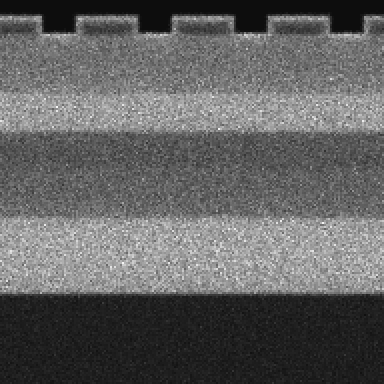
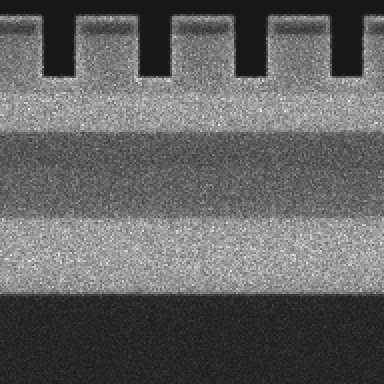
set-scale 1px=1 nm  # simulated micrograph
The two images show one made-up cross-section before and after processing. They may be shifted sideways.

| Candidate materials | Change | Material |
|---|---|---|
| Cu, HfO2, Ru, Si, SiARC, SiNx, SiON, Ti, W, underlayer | removed | W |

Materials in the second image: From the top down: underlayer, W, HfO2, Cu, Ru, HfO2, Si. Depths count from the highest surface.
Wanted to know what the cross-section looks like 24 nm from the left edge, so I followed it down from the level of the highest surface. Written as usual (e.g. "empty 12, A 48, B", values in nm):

underlayer 18, W 60, HfO2 38, Cu 36, Ru 50, HfO2 76, Si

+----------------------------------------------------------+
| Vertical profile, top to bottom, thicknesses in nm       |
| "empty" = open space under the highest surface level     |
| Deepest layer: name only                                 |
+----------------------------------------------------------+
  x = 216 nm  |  underlayer 18, W 60, HfO2 38, Cu 36, Ru 50, HfO2 76, Si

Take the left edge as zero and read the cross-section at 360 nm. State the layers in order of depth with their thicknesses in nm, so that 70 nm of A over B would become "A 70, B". empty 62, W 16, HfO2 38, Cu 36, Ru 50, HfO2 76, Si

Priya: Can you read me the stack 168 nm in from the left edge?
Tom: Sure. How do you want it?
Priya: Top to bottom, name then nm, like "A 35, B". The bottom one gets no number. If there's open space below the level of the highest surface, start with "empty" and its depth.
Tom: empty 62, W 16, HfO2 38, Cu 36, Ru 50, HfO2 76, Si